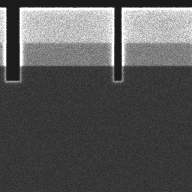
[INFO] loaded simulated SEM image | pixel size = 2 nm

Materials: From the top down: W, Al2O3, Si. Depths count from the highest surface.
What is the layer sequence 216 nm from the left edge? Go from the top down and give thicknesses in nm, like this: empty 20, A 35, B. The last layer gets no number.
W 70, Al2O3 46, Si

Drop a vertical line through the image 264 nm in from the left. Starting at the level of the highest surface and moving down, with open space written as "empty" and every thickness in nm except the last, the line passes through W 70, Al2O3 46, Si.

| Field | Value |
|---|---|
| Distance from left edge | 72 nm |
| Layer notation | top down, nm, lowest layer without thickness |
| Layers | W 70, Al2O3 46, Si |